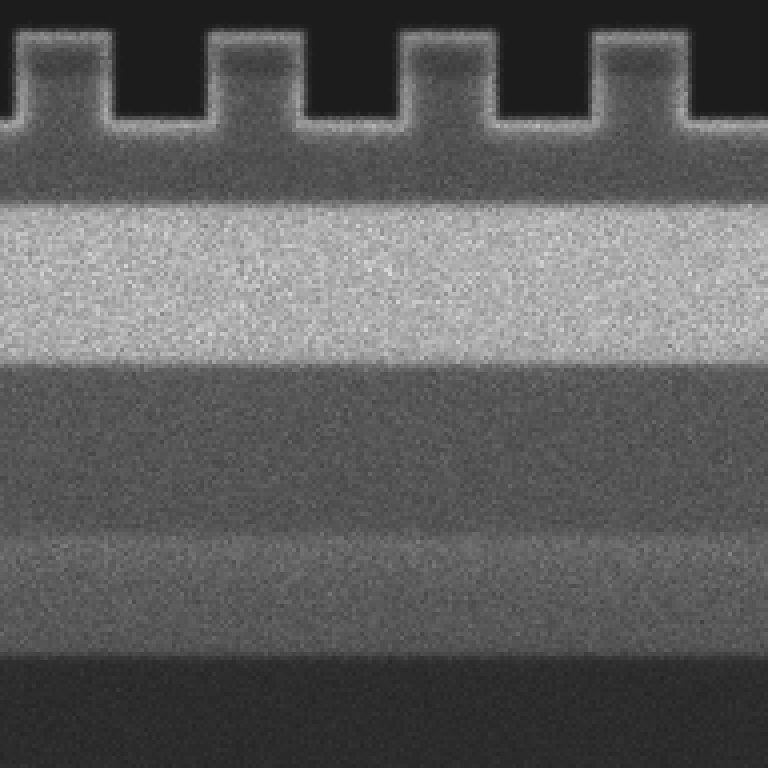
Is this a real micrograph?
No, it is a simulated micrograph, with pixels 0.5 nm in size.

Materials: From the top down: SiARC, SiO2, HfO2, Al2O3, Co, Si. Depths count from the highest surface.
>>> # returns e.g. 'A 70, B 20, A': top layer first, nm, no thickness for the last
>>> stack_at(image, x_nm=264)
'empty 44, SiO2 42, HfO2 80, Al2O3 86, Co 60, Si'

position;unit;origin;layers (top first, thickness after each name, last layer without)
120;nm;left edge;SiARC 22, SiO2 64, HfO2 80, Al2O3 86, Co 60, Si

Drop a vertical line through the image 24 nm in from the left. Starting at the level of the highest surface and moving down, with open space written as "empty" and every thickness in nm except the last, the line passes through SiARC 22, SiO2 64, HfO2 80, Al2O3 86, Co 60, Si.